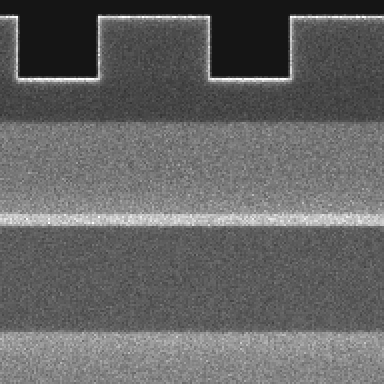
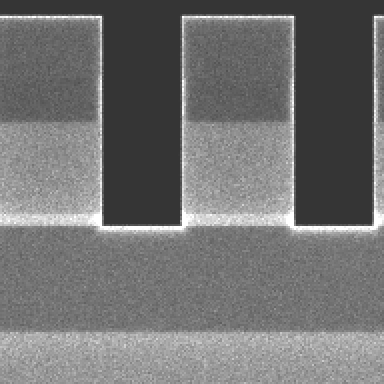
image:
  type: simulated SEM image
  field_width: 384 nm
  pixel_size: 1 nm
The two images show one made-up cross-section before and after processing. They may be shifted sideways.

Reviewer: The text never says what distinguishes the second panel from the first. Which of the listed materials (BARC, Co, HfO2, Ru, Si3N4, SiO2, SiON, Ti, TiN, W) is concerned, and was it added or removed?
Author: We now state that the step removed HfO2 and Ru and Si3N4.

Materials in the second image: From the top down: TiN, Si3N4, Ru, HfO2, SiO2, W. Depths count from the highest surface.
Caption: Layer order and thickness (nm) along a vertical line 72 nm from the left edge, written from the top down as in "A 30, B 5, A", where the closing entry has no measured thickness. TiN 62, Si3N4 44, Ru 92, HfO2 12, SiO2 106, W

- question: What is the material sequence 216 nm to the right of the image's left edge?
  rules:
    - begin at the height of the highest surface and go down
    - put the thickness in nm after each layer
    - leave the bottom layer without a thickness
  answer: TiN 62, Si3N4 44, Ru 92, HfO2 12, SiO2 106, W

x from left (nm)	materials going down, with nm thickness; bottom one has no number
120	empty 210, SiO2 106, W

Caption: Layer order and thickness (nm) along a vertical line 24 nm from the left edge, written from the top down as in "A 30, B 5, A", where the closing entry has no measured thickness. TiN 62, Si3N4 44, Ru 92, HfO2 12, SiO2 106, W